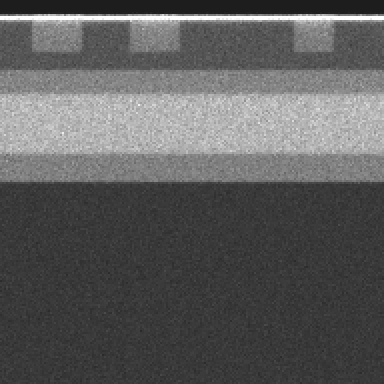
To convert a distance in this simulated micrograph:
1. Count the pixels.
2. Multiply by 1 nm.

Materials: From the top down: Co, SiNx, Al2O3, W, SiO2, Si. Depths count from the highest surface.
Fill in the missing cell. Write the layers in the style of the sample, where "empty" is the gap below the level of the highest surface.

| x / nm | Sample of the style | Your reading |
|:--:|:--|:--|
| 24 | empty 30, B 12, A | SiNx 54, Al2O3 24, W 60, SiO2 28, Si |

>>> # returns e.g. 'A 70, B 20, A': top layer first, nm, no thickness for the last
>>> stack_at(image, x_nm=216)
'SiNx 54, Al2O3 24, W 60, SiO2 28, Si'